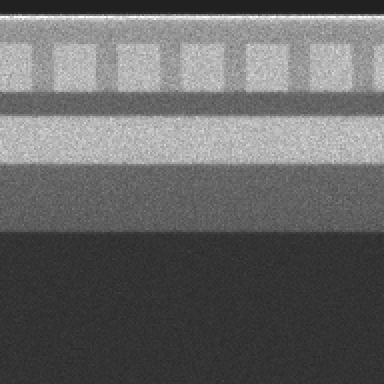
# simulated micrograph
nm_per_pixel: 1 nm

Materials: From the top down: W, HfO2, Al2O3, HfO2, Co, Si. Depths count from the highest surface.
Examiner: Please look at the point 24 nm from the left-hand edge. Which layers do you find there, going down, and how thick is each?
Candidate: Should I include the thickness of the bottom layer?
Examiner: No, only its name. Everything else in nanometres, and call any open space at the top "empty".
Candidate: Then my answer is W 28, HfO2 48, Al2O3 24, HfO2 48, Co 68, Si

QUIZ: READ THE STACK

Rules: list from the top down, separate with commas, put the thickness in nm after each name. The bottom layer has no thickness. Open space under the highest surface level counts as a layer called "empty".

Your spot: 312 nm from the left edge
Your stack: W 28, HfO2 48, Al2O3 24, HfO2 48, Co 68, Si